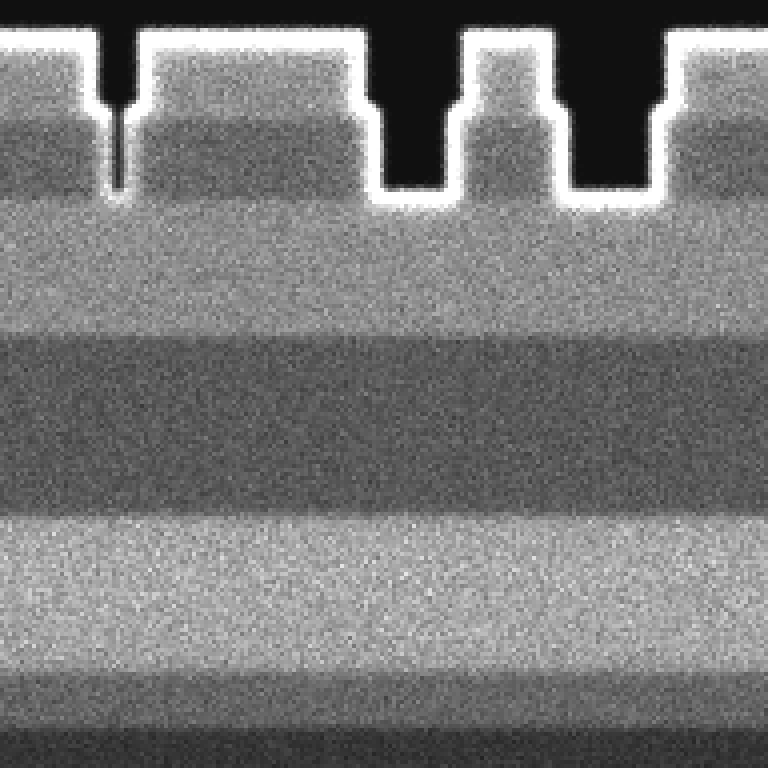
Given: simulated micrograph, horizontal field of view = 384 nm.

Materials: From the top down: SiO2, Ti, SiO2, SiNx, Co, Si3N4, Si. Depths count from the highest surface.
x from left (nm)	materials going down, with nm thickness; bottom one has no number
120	SiO2 44, Ti 40, SiO2 68, SiNx 90, Co 78, Si3N4 28, Si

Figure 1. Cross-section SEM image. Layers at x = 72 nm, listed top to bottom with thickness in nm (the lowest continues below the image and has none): SiO2 44, Ti 40, SiO2 68, SiNx 90, Co 78, Si3N4 28, Si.